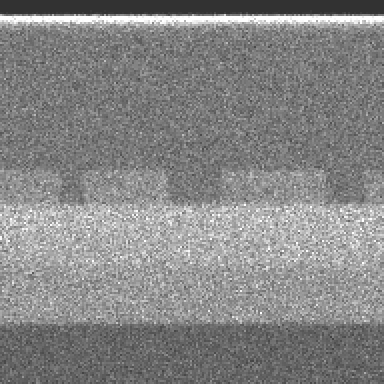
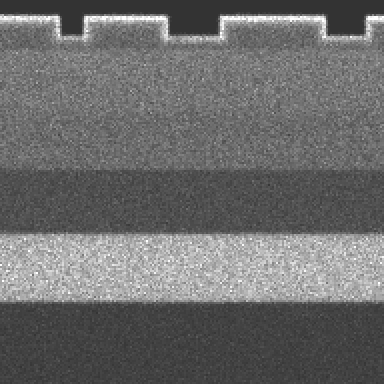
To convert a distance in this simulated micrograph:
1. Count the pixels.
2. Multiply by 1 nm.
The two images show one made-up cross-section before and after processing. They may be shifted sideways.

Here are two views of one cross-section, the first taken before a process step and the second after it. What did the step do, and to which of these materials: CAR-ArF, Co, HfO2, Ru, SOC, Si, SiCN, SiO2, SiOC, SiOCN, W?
It removed SOC.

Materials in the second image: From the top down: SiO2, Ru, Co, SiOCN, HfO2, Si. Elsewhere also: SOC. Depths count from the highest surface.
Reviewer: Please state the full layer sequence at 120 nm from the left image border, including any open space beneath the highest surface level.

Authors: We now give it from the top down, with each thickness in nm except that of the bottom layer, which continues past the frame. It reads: SiO2 34, Ru 62, Co 58, SiOCN 64, HfO2 68, Si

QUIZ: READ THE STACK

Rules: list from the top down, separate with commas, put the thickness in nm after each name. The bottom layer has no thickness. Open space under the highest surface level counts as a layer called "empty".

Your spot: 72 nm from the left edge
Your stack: empty 20, SOC 14, Ru 62, Co 58, SiOCN 64, HfO2 68, Si